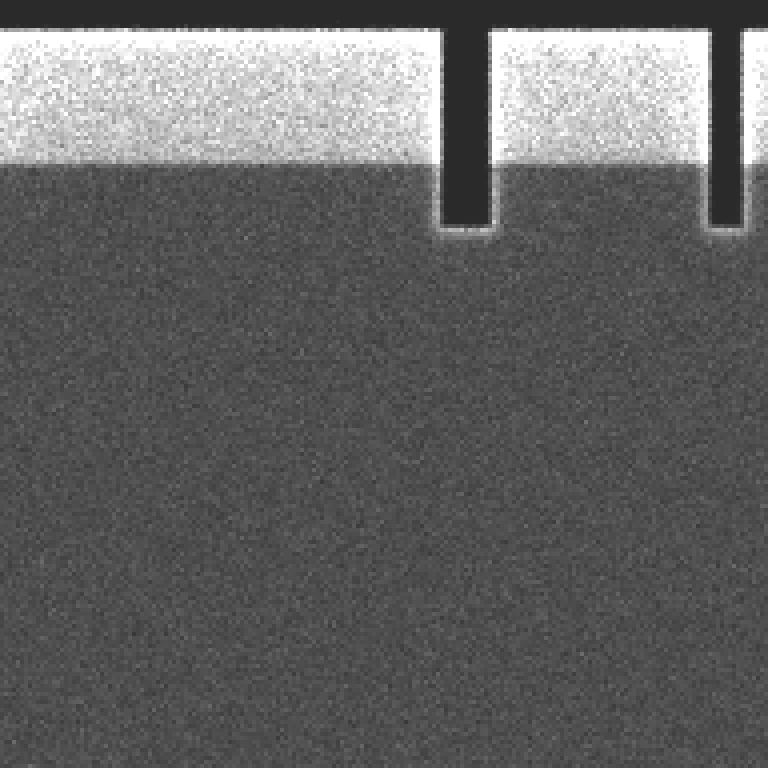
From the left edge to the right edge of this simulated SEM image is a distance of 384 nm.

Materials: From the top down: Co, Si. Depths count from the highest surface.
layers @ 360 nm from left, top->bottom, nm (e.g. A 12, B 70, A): empty 98, Si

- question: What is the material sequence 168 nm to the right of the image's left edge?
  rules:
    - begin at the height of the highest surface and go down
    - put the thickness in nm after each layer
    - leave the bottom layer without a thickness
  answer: Co 66, Si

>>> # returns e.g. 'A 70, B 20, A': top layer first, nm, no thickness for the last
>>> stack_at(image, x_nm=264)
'Co 66, Si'